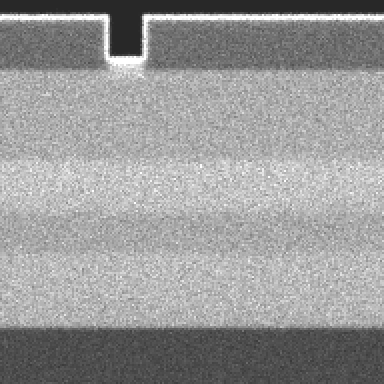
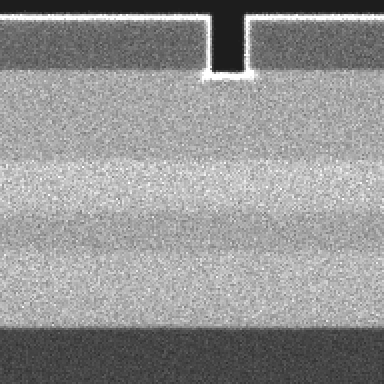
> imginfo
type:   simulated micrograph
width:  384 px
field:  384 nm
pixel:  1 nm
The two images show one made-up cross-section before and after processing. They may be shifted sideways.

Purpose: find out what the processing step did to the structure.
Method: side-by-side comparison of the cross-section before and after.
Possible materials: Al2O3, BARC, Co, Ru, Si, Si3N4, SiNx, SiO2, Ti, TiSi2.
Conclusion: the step removed Ru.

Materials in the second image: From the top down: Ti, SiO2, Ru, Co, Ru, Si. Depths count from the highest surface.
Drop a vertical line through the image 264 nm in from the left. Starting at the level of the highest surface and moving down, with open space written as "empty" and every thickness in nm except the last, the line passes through Ti 54, SiO2 90, Ru 52, Co 40, Ru 76, Si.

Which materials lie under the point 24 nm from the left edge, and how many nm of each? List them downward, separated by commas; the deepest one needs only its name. Ti 54, SiO2 90, Ru 52, Co 40, Ru 76, Si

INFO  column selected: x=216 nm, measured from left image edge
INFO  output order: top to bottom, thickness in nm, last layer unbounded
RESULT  empty 58, Ru 6, SiO2 80, Ru 52, Co 40, Ru 76, Si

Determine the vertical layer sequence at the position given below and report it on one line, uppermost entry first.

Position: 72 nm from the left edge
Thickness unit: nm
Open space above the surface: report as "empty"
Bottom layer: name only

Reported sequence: Ti 54, SiO2 90, Ru 52, Co 40, Ru 76, Si